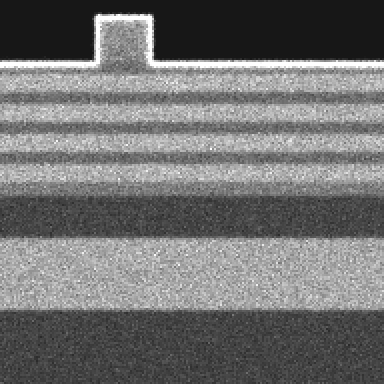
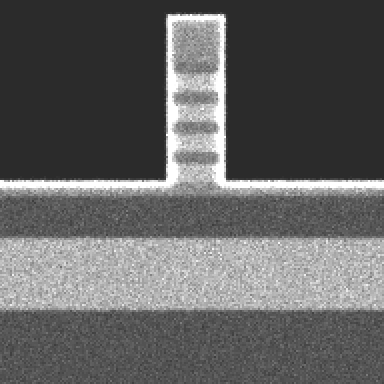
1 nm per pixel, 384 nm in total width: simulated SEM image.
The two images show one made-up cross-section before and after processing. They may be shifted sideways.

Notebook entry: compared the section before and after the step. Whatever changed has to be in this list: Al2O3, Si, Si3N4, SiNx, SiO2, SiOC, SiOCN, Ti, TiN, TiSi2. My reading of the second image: Al2O3 and SiOCN removed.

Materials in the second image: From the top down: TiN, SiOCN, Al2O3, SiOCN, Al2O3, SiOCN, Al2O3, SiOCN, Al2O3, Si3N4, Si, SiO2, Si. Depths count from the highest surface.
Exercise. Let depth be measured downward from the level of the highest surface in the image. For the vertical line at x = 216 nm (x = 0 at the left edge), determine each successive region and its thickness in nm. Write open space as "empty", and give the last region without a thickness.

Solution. TiN 46, SiOCN 12, Al2O3 18, SiOCN 12, Al2O3 18, SiOCN 12, Al2O3 18, SiOCN 12, Al2O3 18, Si3N4 14, Si 42, SiO2 72, Si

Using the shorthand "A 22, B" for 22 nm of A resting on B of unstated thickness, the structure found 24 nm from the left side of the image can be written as empty 166, Si3N4 14, Si 42, SiO2 72, Si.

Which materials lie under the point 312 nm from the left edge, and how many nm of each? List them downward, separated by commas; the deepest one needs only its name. empty 166, Si3N4 14, Si 42, SiO2 72, Si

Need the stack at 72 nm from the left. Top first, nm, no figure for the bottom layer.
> empty 166, Si3N4 14, Si 42, SiO2 72, Si